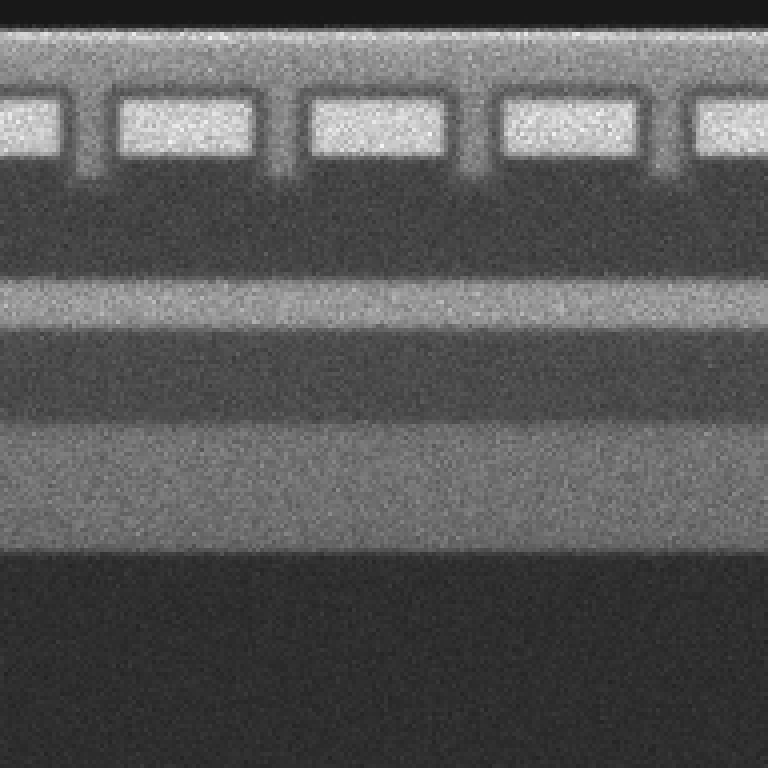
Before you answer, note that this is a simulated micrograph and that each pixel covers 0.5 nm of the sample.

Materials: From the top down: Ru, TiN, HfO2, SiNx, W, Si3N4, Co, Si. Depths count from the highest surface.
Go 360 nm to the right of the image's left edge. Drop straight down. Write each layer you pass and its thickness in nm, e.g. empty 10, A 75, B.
Ru 26, TiN 8, HfO2 28, SiNx 62, W 24, Si3N4 48, Co 64, Si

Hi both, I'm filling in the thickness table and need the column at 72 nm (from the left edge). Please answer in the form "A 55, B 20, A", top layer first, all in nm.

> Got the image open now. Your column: Ru 26, TiN 8, HfO2 28, SiNx 62, W 24, Si3N4 48, Co 64, Si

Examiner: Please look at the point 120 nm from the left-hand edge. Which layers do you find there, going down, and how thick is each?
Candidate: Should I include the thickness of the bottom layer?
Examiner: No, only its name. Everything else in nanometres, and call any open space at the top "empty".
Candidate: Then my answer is Ru 26, TiN 8, HfO2 28, SiNx 62, W 24, Si3N4 48, Co 64, Si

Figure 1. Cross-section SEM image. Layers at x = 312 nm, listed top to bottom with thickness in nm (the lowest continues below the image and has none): Ru 26, TiN 8, HfO2 28, SiNx 62, W 24, Si3N4 48, Co 64, Si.